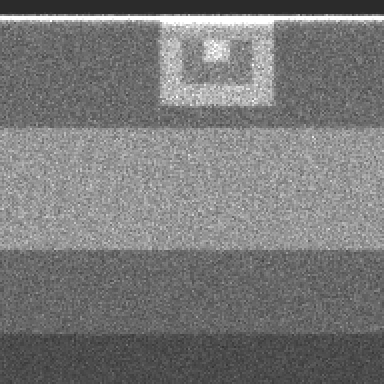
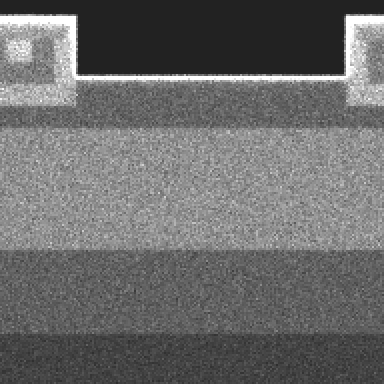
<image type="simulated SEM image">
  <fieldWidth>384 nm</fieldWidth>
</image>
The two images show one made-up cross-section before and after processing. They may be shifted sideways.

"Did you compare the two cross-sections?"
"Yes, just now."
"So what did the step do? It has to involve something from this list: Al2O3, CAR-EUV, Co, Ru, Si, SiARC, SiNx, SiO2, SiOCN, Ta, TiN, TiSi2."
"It removed SiNx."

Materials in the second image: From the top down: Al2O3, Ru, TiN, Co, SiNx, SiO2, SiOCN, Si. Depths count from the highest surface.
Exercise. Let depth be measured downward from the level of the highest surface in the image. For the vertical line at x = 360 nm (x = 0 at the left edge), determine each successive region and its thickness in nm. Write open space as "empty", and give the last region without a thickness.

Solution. Al2O3 24, Co 66, SiNx 22, SiO2 122, SiOCN 84, Si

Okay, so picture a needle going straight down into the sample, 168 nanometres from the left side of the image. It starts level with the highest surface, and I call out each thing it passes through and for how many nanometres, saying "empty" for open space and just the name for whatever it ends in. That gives empty 60, SiNx 52, SiO2 122, SiOCN 84, Si